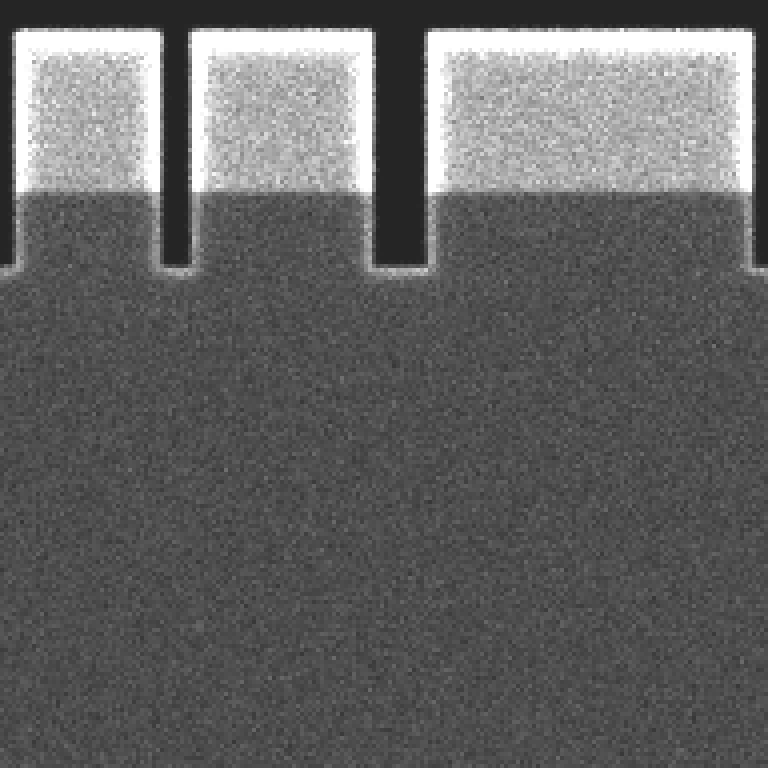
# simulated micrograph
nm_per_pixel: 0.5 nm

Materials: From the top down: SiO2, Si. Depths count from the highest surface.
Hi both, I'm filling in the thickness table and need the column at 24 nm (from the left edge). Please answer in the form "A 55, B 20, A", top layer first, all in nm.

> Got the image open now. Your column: SiO2 80, Si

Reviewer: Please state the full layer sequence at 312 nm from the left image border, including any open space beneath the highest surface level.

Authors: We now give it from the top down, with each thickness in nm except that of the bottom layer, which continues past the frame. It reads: SiO2 80, Si